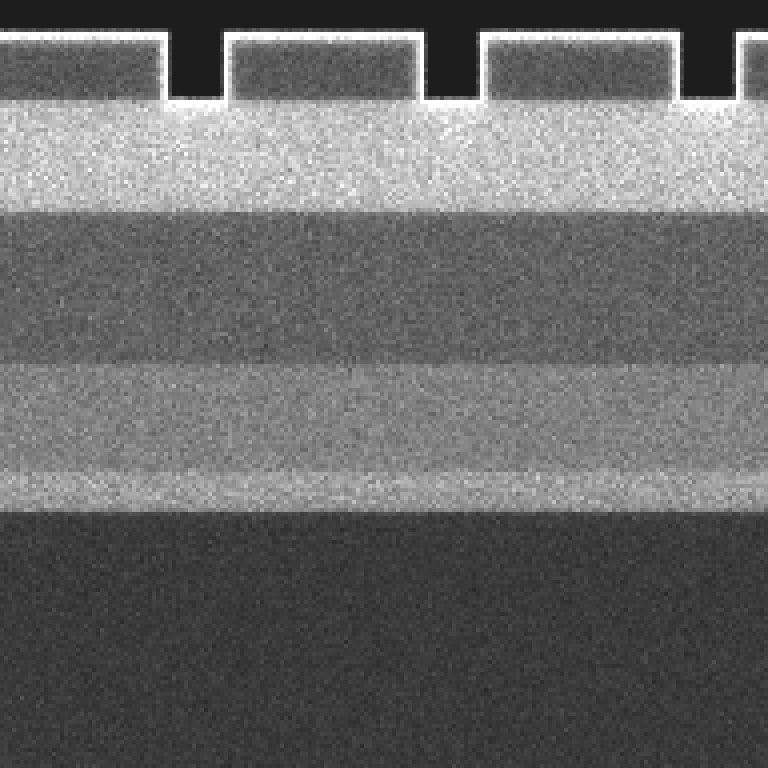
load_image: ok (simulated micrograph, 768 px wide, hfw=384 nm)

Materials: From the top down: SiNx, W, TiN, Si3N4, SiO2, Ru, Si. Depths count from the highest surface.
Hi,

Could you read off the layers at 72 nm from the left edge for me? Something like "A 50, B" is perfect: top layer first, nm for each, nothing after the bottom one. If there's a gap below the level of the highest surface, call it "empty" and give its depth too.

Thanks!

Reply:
SiNx 34, W 56, TiN 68, Si3N4 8, SiO2 54, Ru 20, Si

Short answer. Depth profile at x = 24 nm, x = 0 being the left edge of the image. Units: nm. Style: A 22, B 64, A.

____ SiNx 34, W 56, TiN 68, Si3N4 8, SiO2 54, Ru 20, Si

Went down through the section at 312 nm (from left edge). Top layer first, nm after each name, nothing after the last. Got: SiNx 34, W 56, TiN 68, Si3N4 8, SiO2 54, Ru 20, Si